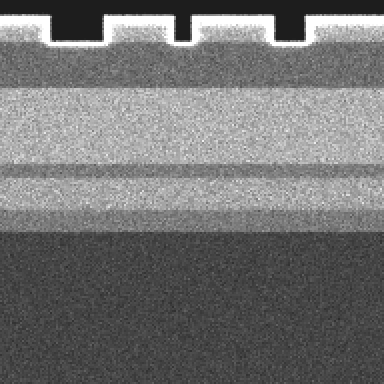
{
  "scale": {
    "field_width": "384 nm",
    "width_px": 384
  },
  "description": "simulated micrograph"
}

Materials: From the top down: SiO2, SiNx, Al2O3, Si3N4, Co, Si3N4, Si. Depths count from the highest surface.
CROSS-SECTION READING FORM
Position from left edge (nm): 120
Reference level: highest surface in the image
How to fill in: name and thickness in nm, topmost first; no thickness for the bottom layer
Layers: SiO2 26, SiNx 46, Al2O3 76, Si3N4 14, Co 32, Si3N4 22, Si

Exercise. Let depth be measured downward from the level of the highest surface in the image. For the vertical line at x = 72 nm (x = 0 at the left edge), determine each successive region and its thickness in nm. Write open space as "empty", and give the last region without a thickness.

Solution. empty 26, SiNx 46, Al2O3 76, Si3N4 14, Co 32, Si3N4 22, Si